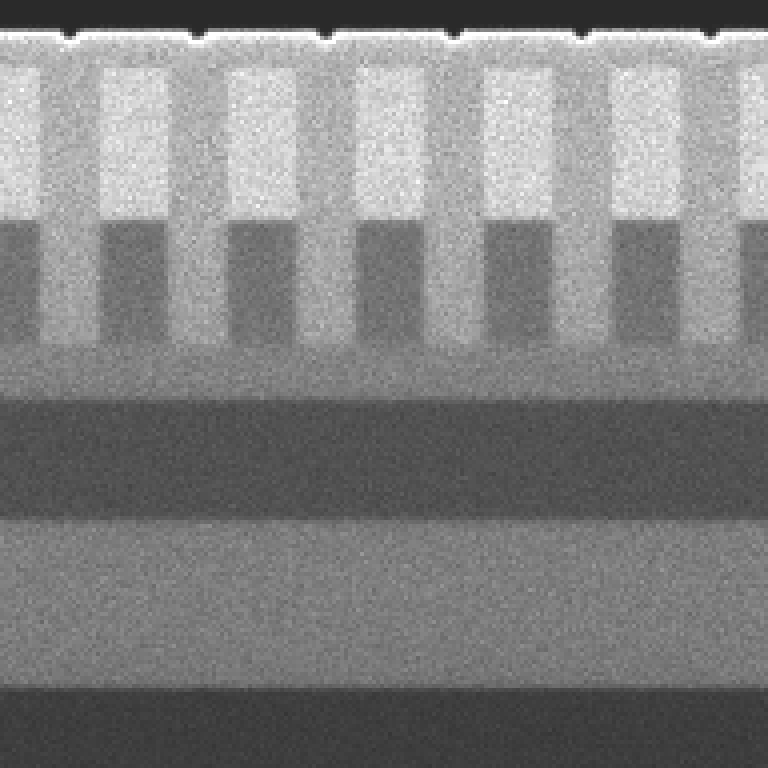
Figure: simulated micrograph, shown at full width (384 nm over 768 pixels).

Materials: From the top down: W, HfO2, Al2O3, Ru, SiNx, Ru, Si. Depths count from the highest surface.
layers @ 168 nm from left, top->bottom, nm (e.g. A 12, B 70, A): W 156, Ru 28, SiNx 60, Ru 84, Si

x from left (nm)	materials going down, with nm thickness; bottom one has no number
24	W 156, Ru 28, SiNx 60, Ru 84, Si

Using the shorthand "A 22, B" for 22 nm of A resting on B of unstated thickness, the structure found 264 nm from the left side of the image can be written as W 18, HfO2 76, Al2O3 62, Ru 28, SiNx 60, Ru 84, Si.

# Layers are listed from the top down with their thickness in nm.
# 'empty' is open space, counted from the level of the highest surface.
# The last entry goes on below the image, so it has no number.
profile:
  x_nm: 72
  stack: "W 18, HfO2 76, Al2O3 62, Ru 28, SiNx 60, Ru 84, Si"